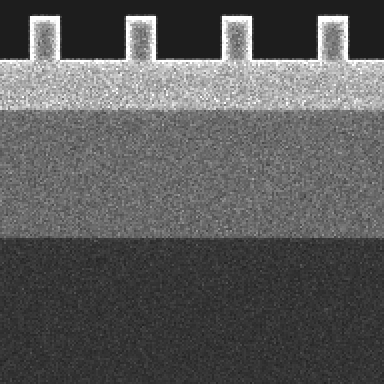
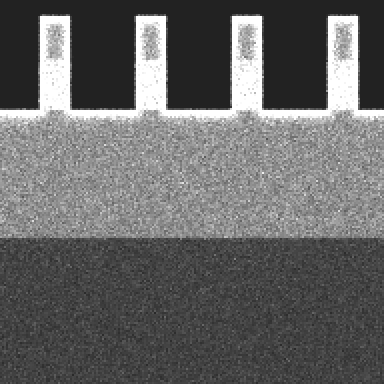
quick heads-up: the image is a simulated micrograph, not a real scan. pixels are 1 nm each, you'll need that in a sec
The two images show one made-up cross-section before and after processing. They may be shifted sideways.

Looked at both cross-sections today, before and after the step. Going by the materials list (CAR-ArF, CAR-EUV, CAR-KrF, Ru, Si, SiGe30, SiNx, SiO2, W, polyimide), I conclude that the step removed W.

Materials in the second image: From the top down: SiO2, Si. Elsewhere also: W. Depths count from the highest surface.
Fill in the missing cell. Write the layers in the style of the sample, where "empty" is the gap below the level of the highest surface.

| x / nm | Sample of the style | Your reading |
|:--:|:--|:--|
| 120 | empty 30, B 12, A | empty 94, SiO2 128, Si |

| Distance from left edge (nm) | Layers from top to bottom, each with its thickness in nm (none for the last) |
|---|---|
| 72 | empty 94, SiO2 128, Si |